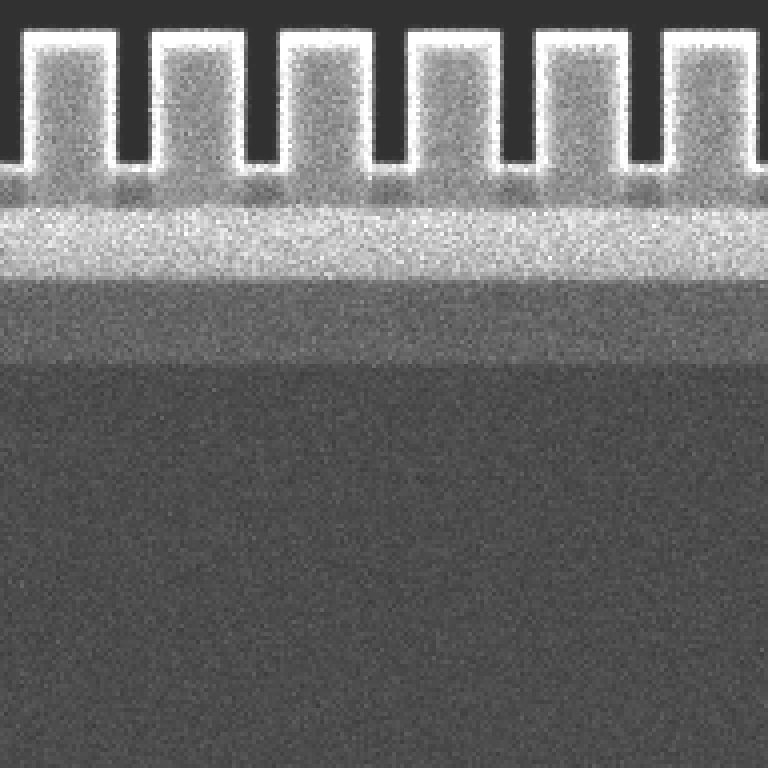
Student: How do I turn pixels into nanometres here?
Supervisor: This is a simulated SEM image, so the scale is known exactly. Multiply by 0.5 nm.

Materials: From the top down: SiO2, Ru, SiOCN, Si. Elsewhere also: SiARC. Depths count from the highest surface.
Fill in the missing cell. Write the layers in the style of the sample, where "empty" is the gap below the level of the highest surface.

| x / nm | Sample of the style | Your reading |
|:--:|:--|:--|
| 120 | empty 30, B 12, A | SiO2 88, Ru 36, SiOCN 42, Si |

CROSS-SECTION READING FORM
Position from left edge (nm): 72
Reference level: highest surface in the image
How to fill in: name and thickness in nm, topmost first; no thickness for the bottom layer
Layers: empty 66, SiARC 22, Ru 36, SiOCN 42, Si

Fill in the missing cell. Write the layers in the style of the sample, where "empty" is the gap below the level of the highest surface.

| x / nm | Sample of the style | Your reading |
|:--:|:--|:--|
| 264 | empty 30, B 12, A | empty 66, SiARC 22, Ru 36, SiOCN 42, Si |